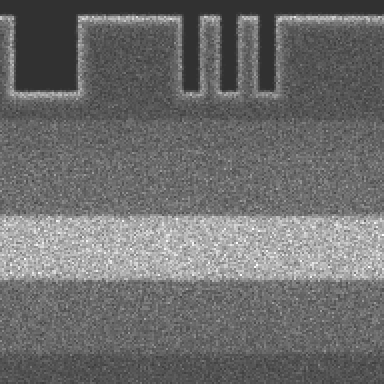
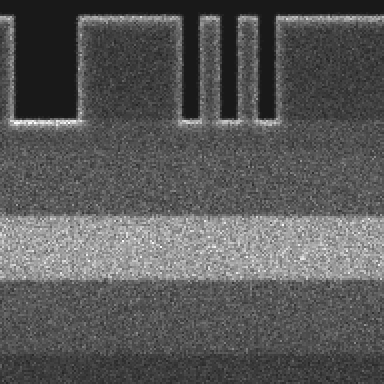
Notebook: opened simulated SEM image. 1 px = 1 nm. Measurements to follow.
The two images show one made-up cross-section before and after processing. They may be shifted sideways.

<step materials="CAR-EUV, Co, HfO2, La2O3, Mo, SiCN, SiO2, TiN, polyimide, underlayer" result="removed underlayer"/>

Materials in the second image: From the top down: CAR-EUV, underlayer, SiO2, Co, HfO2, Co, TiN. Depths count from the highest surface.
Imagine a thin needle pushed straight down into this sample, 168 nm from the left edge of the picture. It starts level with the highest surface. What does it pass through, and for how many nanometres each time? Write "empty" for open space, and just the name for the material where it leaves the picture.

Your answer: CAR-EUV 76, underlayer 28, SiO2 30, Co 66, HfO2 64, Co 74, TiN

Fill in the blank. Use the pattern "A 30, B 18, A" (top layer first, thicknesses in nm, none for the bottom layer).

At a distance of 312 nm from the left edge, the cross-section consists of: CAR-EUV 76, underlayer 28, SiO2 30, Co 66, HfO2 64, Co 74, TiN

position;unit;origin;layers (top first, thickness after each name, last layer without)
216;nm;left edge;CAR-EUV 76, underlayer 28, SiO2 30, Co 66, HfO2 64, Co 74, TiN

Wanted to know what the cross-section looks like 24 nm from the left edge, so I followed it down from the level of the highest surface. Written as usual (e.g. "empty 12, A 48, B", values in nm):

empty 104, SiO2 30, Co 66, HfO2 64, Co 74, TiN